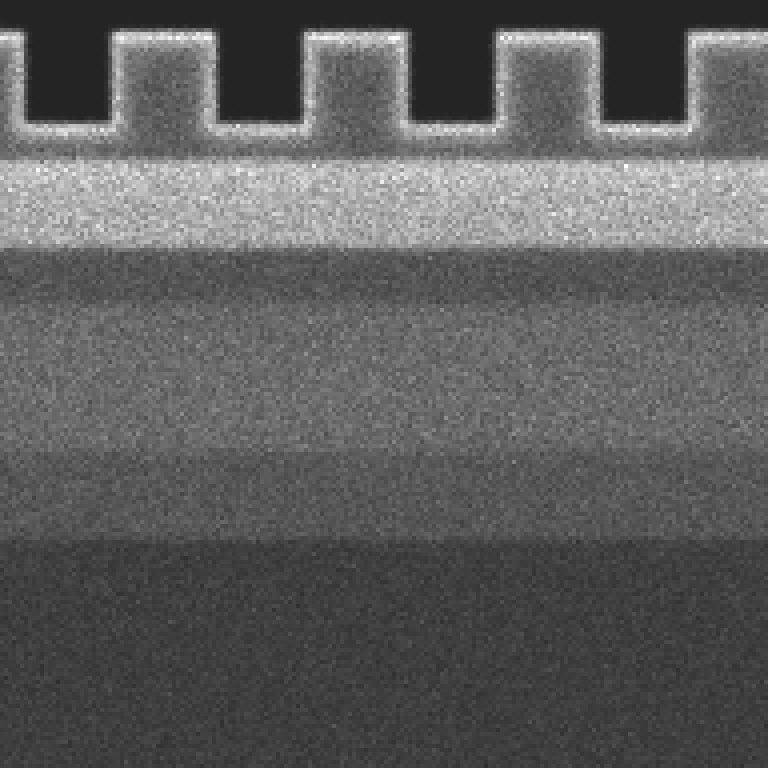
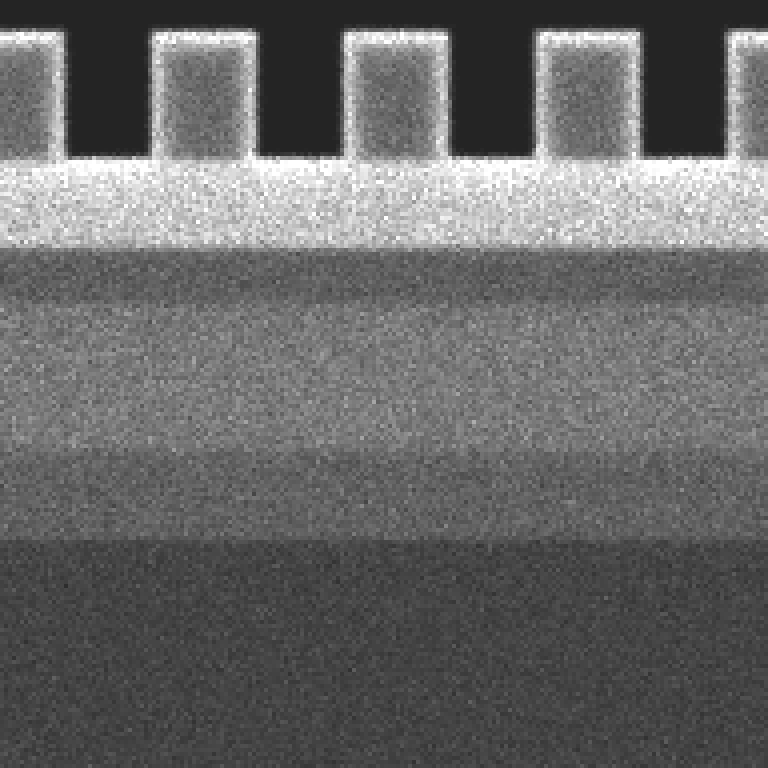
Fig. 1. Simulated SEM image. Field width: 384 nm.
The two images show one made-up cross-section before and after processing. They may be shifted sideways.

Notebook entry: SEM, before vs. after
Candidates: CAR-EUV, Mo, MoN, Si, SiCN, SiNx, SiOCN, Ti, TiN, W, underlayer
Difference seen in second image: underlayer removed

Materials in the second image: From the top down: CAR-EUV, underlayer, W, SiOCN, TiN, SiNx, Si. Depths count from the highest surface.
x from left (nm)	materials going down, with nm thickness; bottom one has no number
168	empty 64, W 44, SiOCN 28, TiN 74, SiNx 44, Si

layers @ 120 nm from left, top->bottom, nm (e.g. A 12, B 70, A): CAR-EUV 46, underlayer 18, W 44, SiOCN 28, TiN 74, SiNx 44, Si